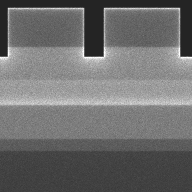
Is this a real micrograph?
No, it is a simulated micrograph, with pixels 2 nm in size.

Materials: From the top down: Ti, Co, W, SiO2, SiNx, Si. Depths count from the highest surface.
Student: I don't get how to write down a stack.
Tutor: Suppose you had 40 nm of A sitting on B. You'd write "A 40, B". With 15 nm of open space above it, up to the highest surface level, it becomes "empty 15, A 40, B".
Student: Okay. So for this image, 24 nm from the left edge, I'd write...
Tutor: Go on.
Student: Ti 78, Co 66, W 50, SiO2 68, SiNx 24, Si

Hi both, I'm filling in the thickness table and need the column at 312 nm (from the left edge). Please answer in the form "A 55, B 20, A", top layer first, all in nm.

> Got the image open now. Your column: Ti 78, Co 66, W 50, SiO2 68, SiNx 24, Si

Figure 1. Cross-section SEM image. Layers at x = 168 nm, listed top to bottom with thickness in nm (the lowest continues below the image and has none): empty 98, Co 46, W 50, SiO2 68, SiNx 24, Si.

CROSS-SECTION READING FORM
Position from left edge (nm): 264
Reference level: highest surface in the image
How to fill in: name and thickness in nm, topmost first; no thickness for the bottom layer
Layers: Ti 78, Co 66, W 50, SiO2 68, SiNx 24, Si